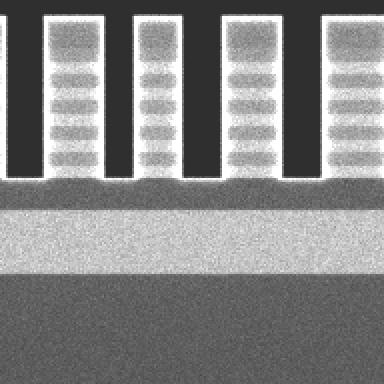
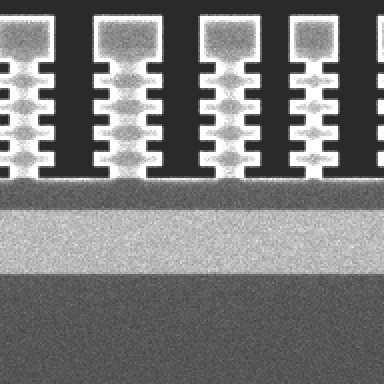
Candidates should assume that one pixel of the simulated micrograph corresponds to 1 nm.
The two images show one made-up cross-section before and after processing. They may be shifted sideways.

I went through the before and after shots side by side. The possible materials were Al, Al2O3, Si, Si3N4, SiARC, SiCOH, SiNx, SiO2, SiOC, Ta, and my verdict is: removed, Al2O3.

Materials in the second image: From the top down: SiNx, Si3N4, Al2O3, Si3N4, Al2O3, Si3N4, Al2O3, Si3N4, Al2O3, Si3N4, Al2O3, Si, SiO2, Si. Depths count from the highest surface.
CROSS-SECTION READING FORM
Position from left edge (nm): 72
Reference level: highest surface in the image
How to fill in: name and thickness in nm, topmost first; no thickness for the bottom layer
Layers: empty 162, Si 32, SiO2 64, Si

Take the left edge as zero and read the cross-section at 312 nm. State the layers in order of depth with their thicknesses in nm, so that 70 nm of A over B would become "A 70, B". SiNx 32, Si3N4 14, Al2O3 12, Si3N4 14, Al2O3 12, Si3N4 14, Al2O3 12, Si3N4 14, Al2O3 12, Si3N4 14, Al2O3 12, Si 32, SiO2 64, Si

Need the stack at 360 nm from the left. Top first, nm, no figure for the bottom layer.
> empty 162, Si 32, SiO2 64, Si